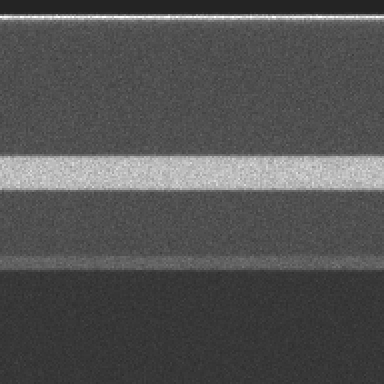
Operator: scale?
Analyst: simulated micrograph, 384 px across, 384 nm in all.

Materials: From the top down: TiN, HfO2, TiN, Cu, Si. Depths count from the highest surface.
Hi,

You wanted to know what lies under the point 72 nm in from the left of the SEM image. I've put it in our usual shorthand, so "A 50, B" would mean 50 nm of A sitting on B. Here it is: TiN 140, HfO2 34, TiN 66, Cu 14, Si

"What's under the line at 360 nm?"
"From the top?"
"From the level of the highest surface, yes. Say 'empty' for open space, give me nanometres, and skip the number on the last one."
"TiN 140, HfO2 34, TiN 66, Cu 14, Si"